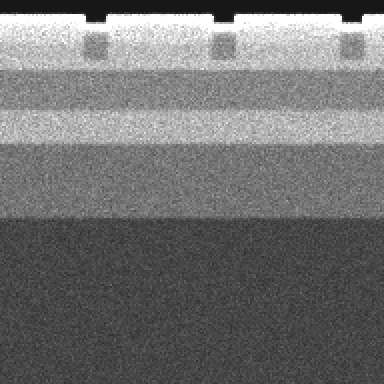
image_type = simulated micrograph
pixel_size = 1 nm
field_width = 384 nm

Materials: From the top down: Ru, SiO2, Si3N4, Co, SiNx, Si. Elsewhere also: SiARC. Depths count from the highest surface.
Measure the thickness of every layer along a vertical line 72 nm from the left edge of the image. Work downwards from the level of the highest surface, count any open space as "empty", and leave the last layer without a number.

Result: Ru 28, SiO2 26, Si3N4 40, Co 34, SiNx 74, Si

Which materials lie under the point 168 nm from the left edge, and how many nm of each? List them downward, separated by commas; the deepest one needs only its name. Ru 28, SiO2 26, Si3N4 40, Co 34, SiNx 74, Si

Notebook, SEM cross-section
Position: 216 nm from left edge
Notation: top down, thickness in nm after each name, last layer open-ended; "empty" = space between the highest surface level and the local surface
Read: empty 8, SiARC 36, SiO2 10, Si3N4 40, Co 34, SiNx 74, Si